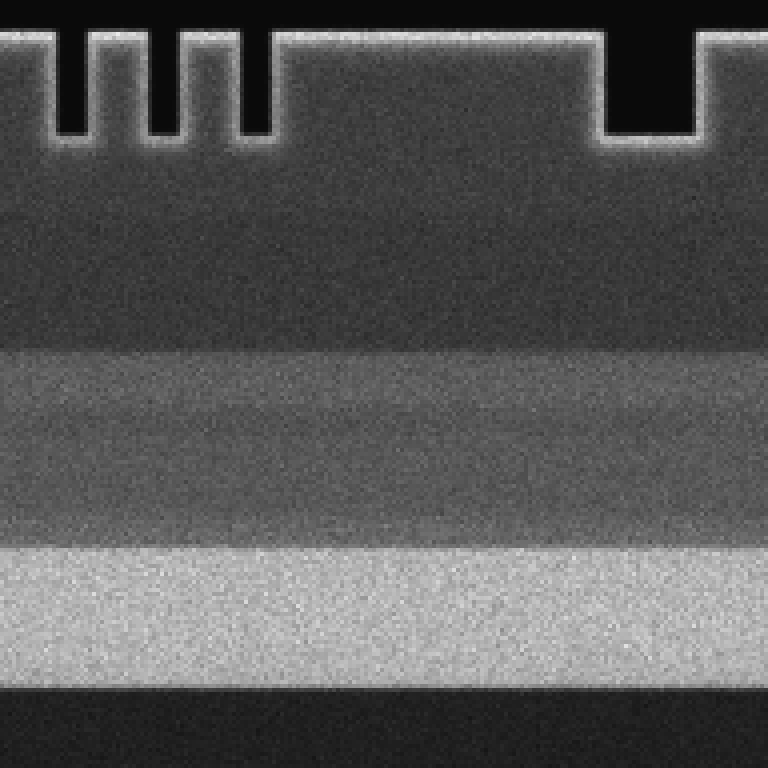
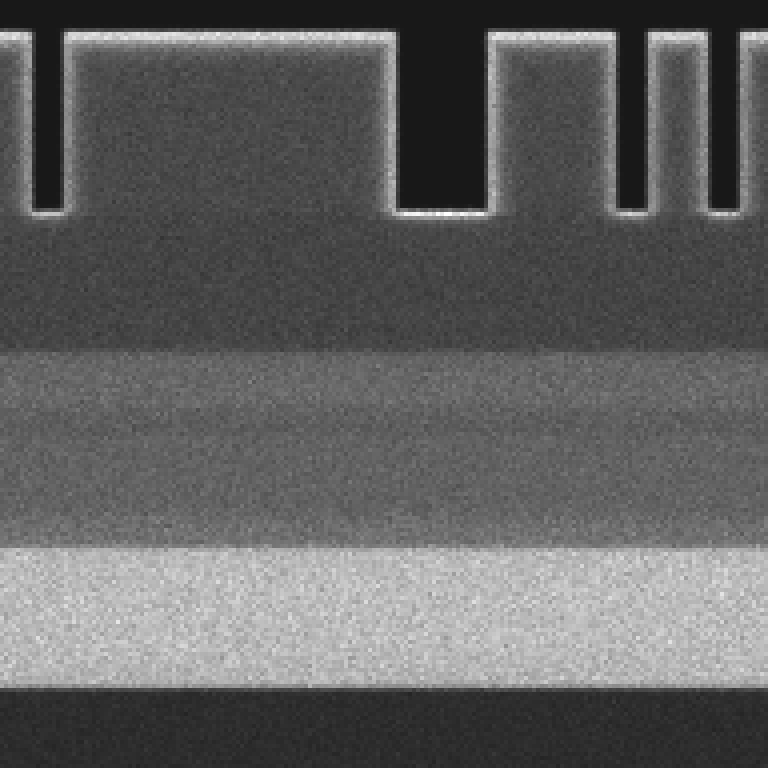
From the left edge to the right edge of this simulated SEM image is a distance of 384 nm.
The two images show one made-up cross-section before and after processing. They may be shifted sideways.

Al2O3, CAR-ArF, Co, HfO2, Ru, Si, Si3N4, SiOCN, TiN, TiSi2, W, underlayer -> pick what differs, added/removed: underlayer removed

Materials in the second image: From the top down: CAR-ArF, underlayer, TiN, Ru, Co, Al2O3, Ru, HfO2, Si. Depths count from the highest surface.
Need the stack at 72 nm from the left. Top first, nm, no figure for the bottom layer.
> CAR-ArF 52, underlayer 38, TiN 70, Ru 28, Co 14, Al2O3 40, Ru 16, HfO2 70, Si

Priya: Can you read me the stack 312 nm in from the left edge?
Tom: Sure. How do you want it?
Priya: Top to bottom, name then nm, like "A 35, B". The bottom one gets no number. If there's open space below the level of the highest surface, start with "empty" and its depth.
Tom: empty 90, TiN 70, Ru 28, Co 14, Al2O3 40, Ru 16, HfO2 70, Si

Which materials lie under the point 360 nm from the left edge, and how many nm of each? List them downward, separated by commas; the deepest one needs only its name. empty 90, TiN 70, Ru 28, Co 14, Al2O3 40, Ru 16, HfO2 70, Si